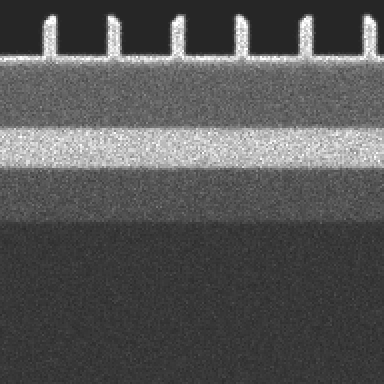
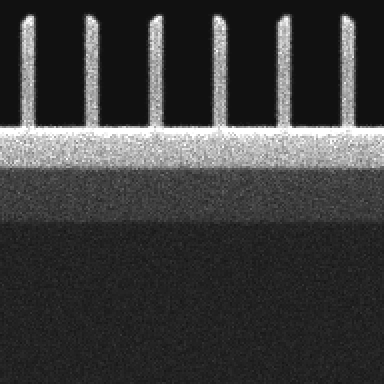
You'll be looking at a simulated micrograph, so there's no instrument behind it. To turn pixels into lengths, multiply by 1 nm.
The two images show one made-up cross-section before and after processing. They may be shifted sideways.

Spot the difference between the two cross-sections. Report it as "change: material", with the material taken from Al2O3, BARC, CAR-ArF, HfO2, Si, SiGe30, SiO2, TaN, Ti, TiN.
removed: SiO2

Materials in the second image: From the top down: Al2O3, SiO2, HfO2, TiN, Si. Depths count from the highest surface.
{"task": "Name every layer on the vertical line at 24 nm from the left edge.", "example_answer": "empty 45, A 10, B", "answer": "empty 4, Al2O3 36, SiO2 72, HfO2 40, TiN 54, Si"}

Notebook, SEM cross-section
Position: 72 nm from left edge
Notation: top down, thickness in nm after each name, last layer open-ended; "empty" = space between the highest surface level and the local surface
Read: empty 112, HfO2 40, TiN 54, Si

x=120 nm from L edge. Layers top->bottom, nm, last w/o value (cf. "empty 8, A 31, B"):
empty 112, HfO2 40, TiN 54, Si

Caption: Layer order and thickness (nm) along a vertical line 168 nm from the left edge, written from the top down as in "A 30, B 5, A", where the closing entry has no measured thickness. empty 112, HfO2 40, TiN 54, Si